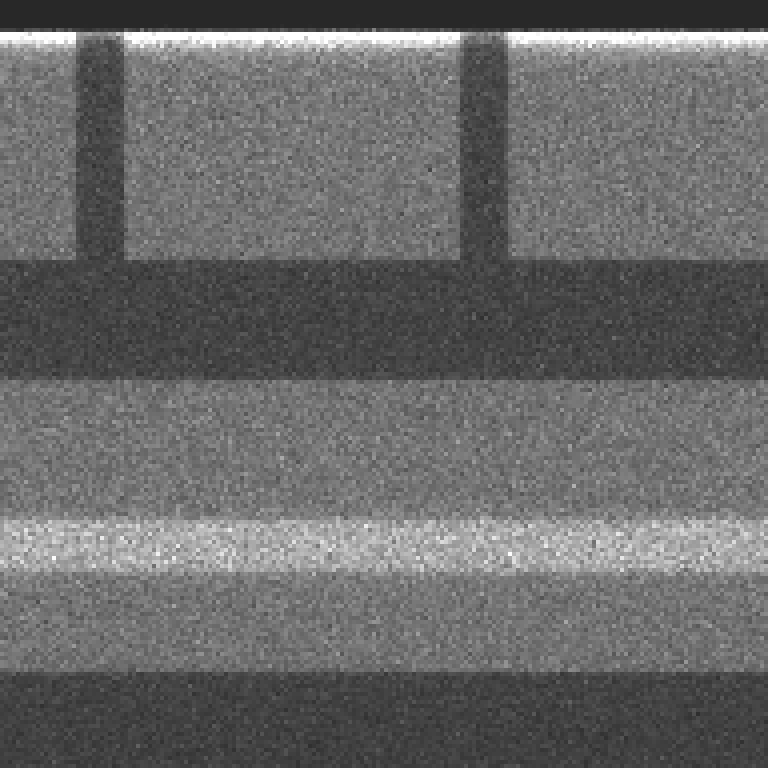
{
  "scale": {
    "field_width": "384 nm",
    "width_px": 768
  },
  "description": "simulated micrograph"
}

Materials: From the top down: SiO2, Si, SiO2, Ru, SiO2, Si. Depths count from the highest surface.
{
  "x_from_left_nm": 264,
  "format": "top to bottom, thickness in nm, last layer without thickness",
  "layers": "SiO2 114, Si 60, SiO2 70, Ru 26, SiO2 50, Si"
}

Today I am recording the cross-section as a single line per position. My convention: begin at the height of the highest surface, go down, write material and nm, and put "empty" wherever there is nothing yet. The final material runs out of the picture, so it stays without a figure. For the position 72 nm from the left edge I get SiO2 114, Si 60, SiO2 70, Ru 26, SiO2 50, Si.